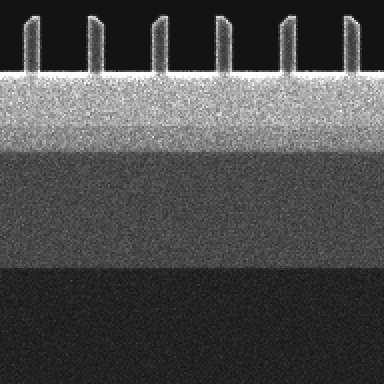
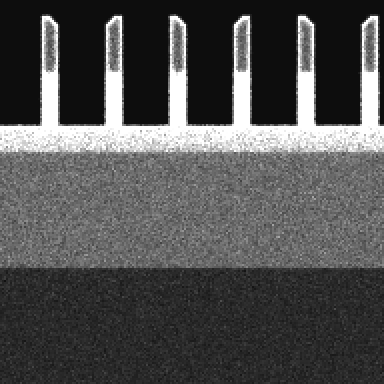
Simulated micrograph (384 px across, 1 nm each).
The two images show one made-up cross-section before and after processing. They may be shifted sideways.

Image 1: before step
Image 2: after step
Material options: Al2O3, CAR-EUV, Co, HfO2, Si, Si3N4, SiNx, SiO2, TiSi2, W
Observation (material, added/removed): HfO2, removed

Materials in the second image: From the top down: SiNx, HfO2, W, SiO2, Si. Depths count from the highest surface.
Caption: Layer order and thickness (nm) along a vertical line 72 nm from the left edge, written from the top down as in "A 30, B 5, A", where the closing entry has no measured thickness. empty 110, W 26, SiO2 116, Si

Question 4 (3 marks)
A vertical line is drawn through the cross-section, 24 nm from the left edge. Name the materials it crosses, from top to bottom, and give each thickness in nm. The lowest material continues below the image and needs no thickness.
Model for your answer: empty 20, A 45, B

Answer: empty 110, W 26, SiO2 116, Si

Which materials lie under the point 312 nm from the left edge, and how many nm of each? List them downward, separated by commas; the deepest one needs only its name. empty 8, SiNx 48, HfO2 54, W 26, SiO2 116, Si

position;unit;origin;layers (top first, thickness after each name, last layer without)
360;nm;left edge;empty 110, W 26, SiO2 116, Si